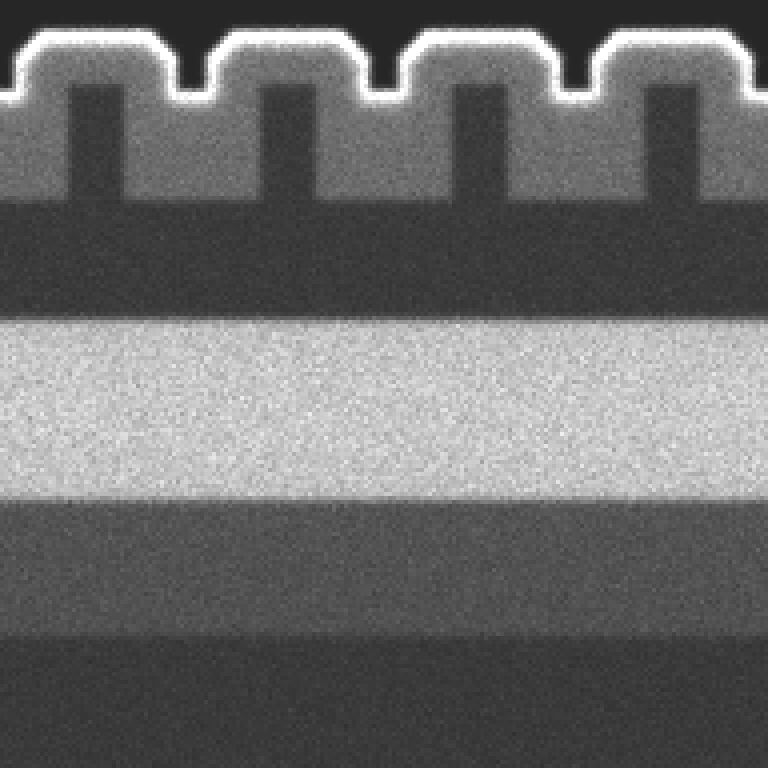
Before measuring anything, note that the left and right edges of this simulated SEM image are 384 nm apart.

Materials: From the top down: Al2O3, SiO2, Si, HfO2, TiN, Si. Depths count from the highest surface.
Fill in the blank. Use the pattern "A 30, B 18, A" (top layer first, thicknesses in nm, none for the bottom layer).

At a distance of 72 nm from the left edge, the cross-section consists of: Al2O3 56, SiO2 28, Si 60, HfO2 90, TiN 68, Si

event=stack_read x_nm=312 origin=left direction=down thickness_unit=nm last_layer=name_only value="Al2O3 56, SiO2 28, Si 60, HfO2 90, TiN 68, Si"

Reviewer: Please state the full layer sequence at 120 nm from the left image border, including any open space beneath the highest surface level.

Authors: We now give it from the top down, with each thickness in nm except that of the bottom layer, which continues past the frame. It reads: Al2O3 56, SiO2 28, Si 60, HfO2 90, TiN 68, Si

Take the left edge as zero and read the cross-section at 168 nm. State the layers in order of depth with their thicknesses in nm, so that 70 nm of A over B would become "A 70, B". Al2O3 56, SiO2 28, Si 60, HfO2 90, TiN 68, Si